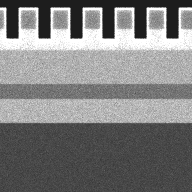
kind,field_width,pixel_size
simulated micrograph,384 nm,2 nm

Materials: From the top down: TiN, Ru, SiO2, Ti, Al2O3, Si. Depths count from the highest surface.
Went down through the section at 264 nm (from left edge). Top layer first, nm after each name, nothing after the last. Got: TiN 42, Ru 42, SiO2 68, Ti 30, Al2O3 48, Si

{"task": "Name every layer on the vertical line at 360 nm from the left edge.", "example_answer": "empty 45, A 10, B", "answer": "TiN 42, Ru 42, SiO2 68, Ti 30, Al2O3 48, Si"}